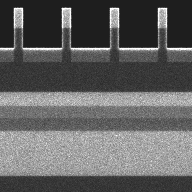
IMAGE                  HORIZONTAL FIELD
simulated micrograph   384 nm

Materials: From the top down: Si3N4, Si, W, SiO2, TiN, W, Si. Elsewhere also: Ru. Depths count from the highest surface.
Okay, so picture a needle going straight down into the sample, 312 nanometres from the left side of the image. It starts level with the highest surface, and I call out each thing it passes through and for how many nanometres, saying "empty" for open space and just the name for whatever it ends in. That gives empty 80, Si3N4 28, Si 60, W 28, SiO2 24, TiN 26, W 90, Si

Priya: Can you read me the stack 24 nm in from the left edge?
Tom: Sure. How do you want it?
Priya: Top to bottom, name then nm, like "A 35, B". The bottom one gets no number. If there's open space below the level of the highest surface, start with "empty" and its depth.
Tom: empty 80, Si3N4 28, Si 60, W 28, SiO2 24, TiN 26, W 90, Si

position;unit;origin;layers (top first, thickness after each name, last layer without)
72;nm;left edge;empty 80, Si3N4 28, Si 60, W 28, SiO2 24, TiN 26, W 90, Si